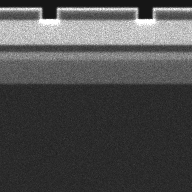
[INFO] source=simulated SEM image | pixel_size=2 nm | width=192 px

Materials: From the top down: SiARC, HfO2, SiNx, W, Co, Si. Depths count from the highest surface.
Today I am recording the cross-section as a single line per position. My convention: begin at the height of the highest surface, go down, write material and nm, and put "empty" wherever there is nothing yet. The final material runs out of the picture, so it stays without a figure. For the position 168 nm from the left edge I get SiARC 24, HfO2 50, SiNx 14, W 16, Co 48, Si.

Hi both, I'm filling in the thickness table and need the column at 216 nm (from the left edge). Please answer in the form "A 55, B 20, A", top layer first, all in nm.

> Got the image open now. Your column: SiARC 24, HfO2 50, SiNx 14, W 16, Co 48, Si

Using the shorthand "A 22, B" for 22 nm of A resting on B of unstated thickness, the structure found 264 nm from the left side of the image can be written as SiARC 24, HfO2 50, SiNx 14, W 16, Co 48, Si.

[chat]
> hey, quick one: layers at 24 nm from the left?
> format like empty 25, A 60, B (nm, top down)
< SiARC 24, HfO2 50, SiNx 14, W 16, Co 48, Si